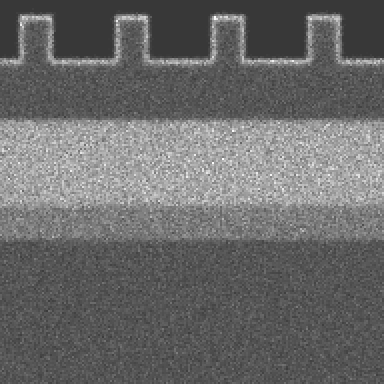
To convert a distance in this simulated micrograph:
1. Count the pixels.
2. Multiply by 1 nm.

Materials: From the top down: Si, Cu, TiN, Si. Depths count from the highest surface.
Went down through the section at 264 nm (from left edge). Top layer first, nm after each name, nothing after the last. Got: empty 44, Si 60, Cu 86, TiN 34, Si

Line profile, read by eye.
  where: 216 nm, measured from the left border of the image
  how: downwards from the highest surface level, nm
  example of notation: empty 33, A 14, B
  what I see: Si 104, Cu 86, TiN 34, Si